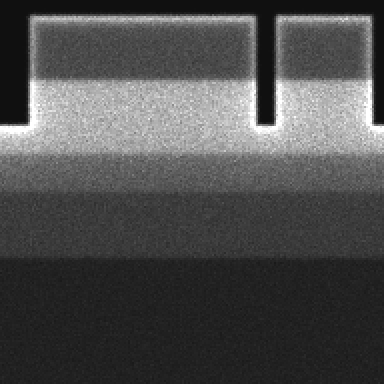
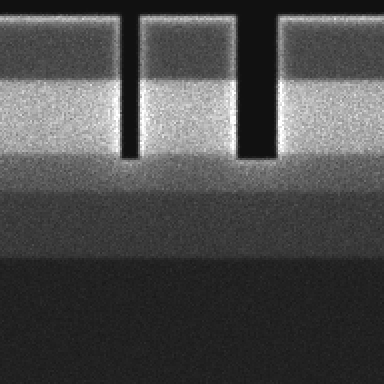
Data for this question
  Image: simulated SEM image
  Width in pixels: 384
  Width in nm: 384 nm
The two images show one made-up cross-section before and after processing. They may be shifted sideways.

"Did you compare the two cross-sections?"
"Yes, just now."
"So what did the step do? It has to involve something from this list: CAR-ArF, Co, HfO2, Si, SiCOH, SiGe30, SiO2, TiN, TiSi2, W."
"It removed Co and HfO2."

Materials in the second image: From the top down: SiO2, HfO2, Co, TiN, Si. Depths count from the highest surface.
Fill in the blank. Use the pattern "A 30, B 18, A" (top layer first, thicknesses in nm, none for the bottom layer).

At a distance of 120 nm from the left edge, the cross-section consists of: empty 144, Co 32, TiN 66, Si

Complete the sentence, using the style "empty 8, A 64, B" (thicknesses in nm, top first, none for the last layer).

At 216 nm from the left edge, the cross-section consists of SiO2 64, HfO2 74, Co 38, TiN 66, Si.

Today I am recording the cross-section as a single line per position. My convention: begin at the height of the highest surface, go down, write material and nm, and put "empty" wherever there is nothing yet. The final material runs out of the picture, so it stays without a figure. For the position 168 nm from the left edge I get SiO2 64, HfO2 74, Co 38, TiN 66, Si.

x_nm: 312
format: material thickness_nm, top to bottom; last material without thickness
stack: SiO2 64, HfO2 74, Co 38, TiN 66, Si